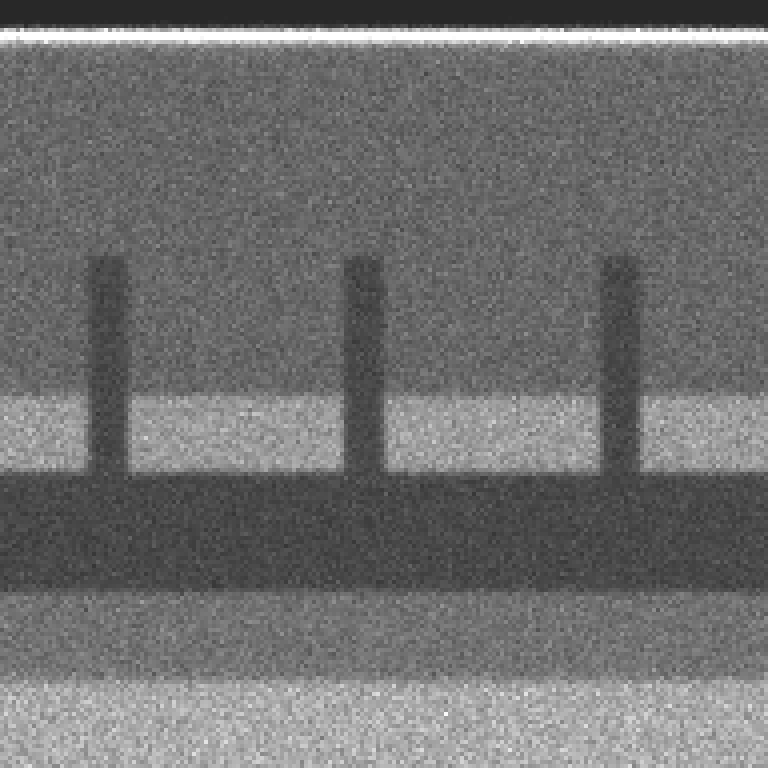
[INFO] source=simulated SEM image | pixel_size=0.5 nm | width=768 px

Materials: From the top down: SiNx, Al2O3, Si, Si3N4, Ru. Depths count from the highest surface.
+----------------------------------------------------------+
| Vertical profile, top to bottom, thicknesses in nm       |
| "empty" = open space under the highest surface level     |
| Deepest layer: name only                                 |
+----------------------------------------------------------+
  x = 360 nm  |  SiNx 182, Al2O3 38, Si 60, Si3N4 44, Ru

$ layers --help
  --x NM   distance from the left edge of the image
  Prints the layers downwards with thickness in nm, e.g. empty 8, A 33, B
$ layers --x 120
SiNx 182, Al2O3 38, Si 60, Si3N4 44, Ru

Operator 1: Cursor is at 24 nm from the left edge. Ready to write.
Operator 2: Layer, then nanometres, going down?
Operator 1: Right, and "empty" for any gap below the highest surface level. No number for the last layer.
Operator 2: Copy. SiNx 182, Al2O3 38, Si 60, Si3N4 44, Ru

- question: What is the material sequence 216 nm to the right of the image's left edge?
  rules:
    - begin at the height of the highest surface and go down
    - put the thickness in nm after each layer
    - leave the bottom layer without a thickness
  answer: SiNx 182, Al2O3 38, Si 60, Si3N4 44, Ru